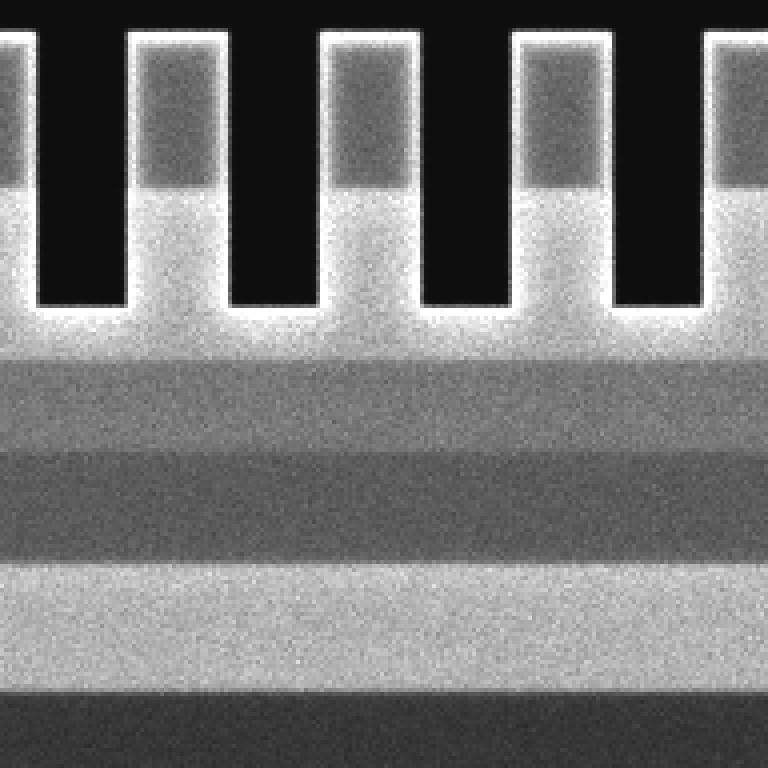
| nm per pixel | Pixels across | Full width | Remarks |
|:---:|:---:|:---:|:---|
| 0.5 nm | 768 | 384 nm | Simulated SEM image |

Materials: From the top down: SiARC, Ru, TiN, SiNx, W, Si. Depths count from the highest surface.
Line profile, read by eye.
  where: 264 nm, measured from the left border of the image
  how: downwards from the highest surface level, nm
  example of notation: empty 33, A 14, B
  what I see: SiARC 78, Ru 86, TiN 46, SiNx 56, W 64, Si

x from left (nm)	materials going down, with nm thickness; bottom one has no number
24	empty 138, Ru 26, TiN 46, SiNx 56, W 64, Si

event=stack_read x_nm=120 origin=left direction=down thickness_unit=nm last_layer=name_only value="empty 138, Ru 26, TiN 46, SiNx 56, W 64, Si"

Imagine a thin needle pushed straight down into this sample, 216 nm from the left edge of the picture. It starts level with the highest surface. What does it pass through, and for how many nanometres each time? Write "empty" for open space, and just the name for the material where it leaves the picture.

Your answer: empty 138, Ru 26, TiN 46, SiNx 56, W 64, Si